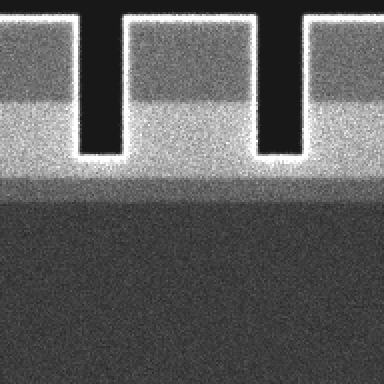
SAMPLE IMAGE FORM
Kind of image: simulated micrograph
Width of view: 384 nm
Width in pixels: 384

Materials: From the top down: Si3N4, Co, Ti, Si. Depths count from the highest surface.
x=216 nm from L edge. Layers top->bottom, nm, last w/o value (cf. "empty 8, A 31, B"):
Si3N4 86, Co 76, Ti 24, Si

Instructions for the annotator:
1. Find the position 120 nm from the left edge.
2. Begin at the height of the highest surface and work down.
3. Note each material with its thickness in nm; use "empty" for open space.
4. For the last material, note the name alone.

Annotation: empty 140, Co 22, Ti 24, Si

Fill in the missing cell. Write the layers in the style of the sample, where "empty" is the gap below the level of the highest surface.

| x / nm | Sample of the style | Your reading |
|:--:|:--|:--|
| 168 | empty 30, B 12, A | Si3N4 86, Co 76, Ti 24, Si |